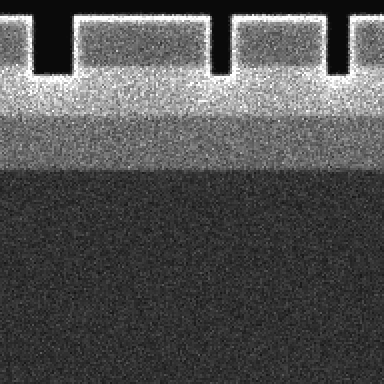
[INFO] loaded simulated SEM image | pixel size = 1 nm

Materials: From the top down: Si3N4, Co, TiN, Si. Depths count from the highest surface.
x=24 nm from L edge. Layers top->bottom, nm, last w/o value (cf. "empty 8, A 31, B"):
Si3N4 50, Co 50, TiN 54, Si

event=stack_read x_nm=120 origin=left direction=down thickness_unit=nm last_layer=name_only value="Si3N4 50, Co 50, TiN 54, Si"